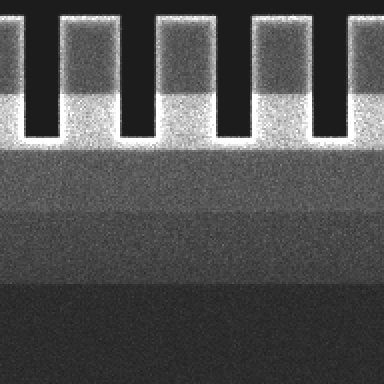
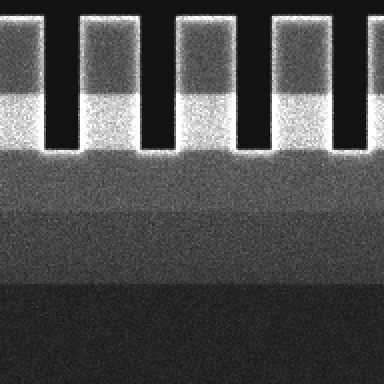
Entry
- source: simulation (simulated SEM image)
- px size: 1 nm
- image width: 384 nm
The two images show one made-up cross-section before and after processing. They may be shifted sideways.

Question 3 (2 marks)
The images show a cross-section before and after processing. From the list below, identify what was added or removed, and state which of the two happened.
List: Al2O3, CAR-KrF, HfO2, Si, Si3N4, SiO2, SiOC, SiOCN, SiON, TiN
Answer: HfO2 was removed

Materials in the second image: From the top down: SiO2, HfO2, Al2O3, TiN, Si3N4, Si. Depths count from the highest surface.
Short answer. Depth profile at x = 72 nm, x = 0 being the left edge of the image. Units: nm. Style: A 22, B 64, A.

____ empty 134, Al2O3 62, TiN 52, Si3N4 20, Si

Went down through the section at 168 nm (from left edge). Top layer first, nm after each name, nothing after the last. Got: empty 134, Al2O3 62, TiN 52, Si3N4 20, Si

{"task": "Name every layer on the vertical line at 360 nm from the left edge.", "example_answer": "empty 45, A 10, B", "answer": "empty 134, Al2O3 62, TiN 52, Si3N4 20, Si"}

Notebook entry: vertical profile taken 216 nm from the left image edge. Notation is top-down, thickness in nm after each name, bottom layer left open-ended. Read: SiO2 78, HfO2 56, Al2O3 62, TiN 52, Si3N4 20, Si